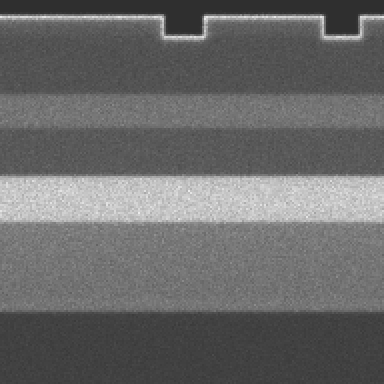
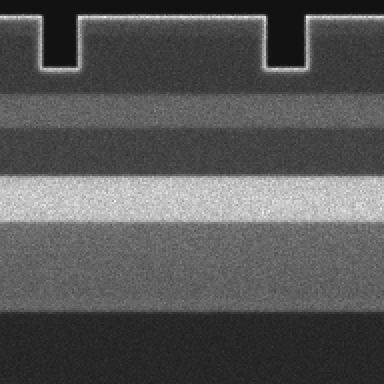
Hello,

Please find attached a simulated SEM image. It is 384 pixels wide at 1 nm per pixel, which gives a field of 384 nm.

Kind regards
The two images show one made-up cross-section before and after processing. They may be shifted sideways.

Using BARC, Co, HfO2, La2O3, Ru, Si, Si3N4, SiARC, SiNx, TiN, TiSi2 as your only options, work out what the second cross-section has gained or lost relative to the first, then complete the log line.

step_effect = removed SiNx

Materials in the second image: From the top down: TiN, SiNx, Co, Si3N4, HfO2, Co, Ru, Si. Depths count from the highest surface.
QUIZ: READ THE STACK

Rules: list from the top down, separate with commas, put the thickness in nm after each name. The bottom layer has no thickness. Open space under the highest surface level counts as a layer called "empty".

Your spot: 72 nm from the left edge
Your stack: empty 52, SiNx 26, Co 34, Si3N4 48, HfO2 46, Co 78, Ru 12, Si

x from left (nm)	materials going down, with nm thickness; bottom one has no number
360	TiN 20, SiNx 58, Co 34, Si3N4 48, HfO2 46, Co 78, Ru 12, Si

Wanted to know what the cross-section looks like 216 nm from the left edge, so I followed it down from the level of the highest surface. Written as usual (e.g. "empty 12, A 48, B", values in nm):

TiN 20, SiNx 58, Co 34, Si3N4 48, HfO2 46, Co 78, Ru 12, Si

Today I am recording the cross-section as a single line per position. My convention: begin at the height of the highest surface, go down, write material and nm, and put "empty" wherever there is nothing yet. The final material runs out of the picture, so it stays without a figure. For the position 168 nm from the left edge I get TiN 20, SiNx 58, Co 34, Si3N4 48, HfO2 46, Co 78, Ru 12, Si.